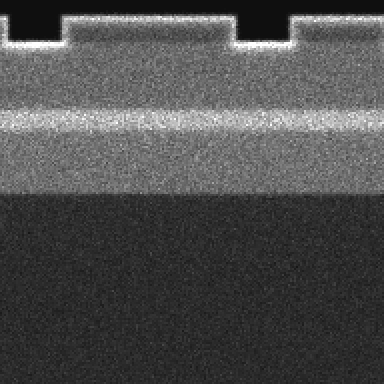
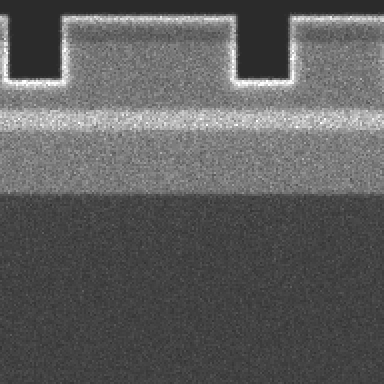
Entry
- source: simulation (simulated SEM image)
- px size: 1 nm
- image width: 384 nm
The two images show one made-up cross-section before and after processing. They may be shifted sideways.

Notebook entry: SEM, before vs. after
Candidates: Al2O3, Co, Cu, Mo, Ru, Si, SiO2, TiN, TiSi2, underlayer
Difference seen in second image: SiO2 removed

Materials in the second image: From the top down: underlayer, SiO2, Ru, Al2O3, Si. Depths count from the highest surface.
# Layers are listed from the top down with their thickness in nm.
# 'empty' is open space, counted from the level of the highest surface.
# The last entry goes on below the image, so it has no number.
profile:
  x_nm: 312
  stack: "underlayer 26, SiO2 68, Ru 20, Al2O3 64, Si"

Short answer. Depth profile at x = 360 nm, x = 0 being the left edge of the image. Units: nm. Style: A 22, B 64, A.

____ underlayer 26, SiO2 68, Ru 20, Al2O3 64, Si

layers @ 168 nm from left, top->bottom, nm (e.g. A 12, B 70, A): underlayer 26, SiO2 68, Ru 20, Al2O3 64, Si